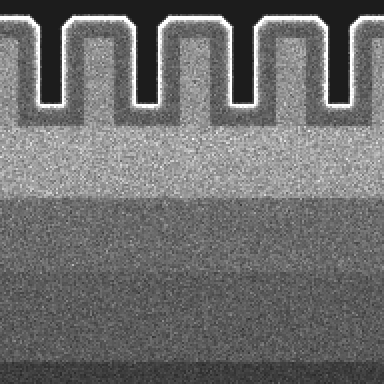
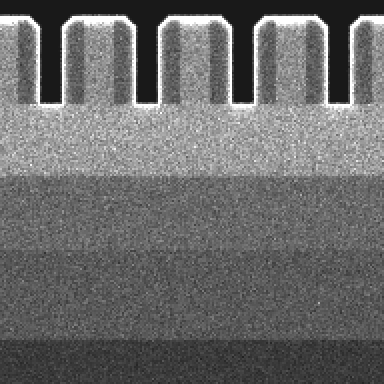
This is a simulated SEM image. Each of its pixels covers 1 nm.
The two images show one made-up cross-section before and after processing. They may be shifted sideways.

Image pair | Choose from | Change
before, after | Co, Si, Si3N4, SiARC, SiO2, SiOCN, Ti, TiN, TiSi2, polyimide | SiOCN (removed)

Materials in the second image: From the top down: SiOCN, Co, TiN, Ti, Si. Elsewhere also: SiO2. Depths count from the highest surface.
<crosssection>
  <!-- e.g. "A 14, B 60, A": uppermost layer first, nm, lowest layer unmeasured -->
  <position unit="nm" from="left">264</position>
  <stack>SiOCN 88, Co 72, TiN 74, Ti 90, Si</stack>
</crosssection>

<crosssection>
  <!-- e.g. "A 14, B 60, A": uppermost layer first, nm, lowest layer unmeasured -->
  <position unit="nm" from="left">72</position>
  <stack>SiOCN 88, Co 72, TiN 74, Ti 90, Si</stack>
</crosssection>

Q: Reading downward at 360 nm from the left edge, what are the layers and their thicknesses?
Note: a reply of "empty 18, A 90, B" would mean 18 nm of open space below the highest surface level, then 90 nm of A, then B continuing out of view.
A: SiOCN 88, Co 72, TiN 74, Ti 90, Si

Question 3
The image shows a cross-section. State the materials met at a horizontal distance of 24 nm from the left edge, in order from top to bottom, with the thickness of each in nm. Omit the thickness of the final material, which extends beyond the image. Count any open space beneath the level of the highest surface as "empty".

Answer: SiOCN 88, Co 72, TiN 74, Ti 90, Si